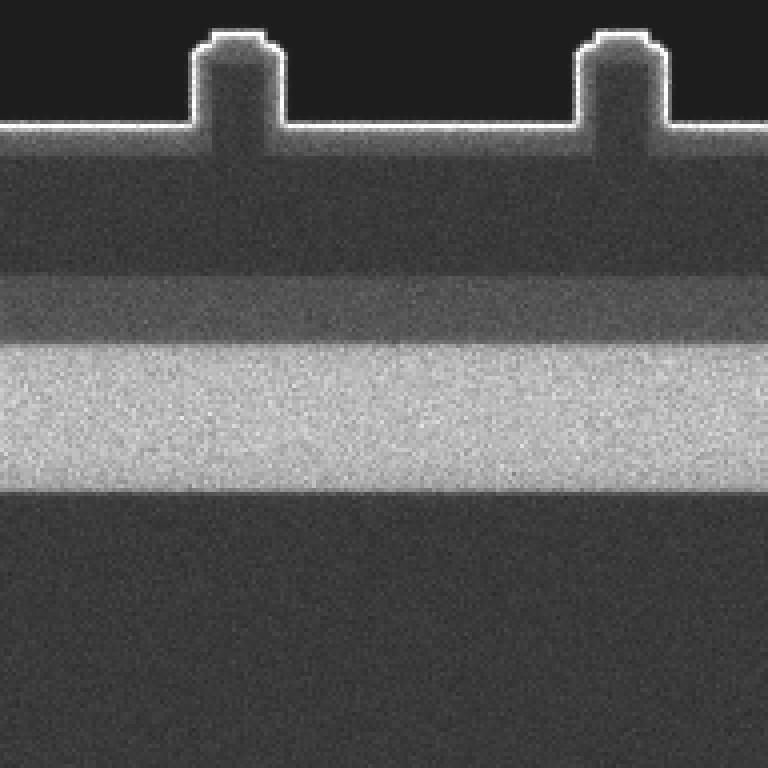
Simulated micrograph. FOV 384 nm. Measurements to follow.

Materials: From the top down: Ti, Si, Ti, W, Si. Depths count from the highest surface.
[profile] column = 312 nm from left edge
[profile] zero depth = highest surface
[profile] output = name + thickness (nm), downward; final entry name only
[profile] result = Ti 16, Si 106, Ti 34, W 74, Si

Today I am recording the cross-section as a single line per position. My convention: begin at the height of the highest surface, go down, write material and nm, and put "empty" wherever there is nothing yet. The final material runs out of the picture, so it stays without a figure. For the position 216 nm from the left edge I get empty 46, Ti 16, Si 60, Ti 34, W 74, Si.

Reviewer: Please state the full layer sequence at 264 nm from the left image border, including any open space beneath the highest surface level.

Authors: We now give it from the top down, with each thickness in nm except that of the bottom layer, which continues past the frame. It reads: empty 46, Ti 16, Si 60, Ti 34, W 74, Si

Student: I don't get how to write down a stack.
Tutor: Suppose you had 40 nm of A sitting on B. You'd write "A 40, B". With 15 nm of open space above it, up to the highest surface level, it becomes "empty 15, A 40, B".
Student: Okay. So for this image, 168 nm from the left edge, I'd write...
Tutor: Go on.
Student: empty 46, Ti 16, Si 60, Ti 34, W 74, Si